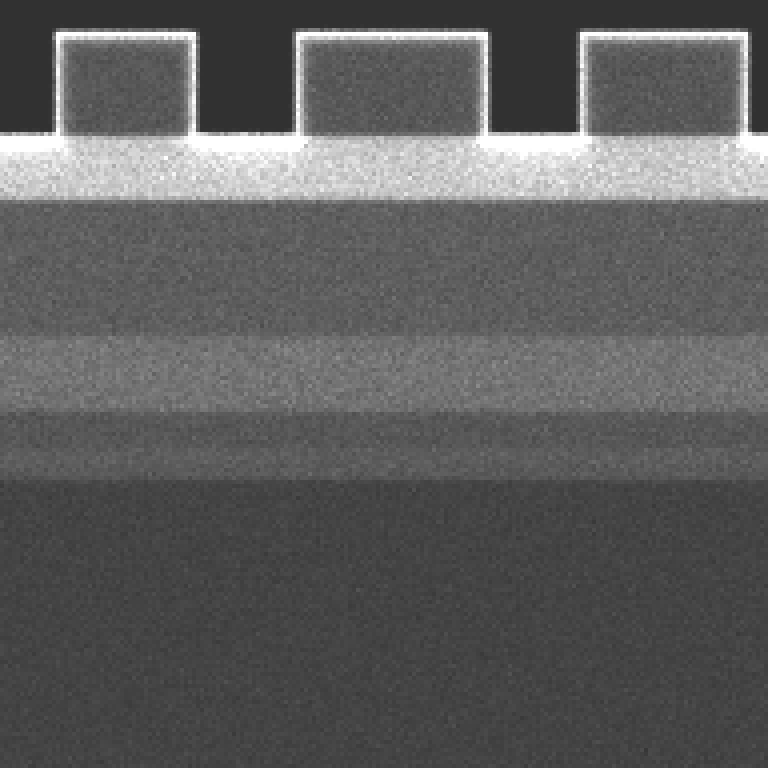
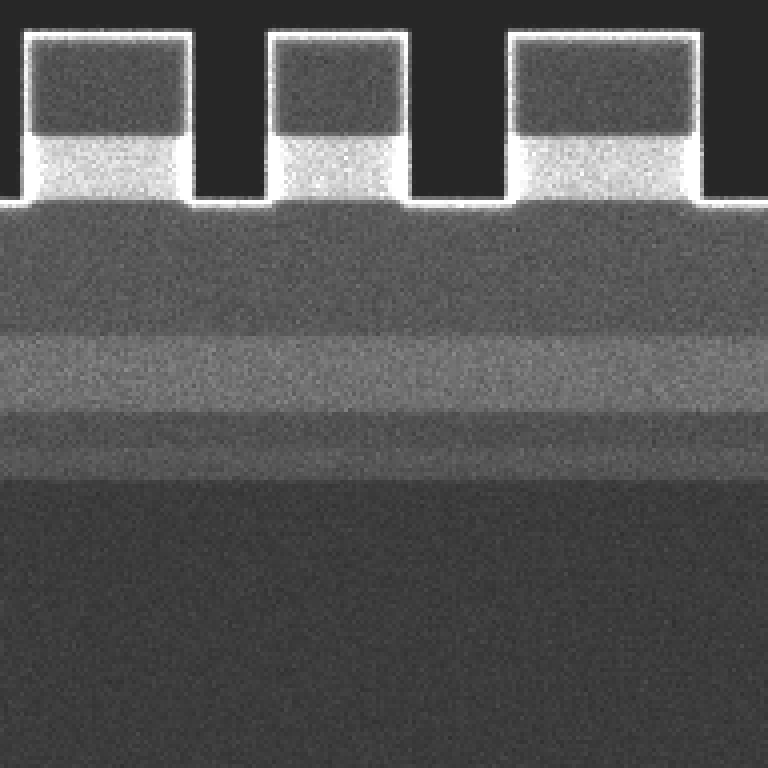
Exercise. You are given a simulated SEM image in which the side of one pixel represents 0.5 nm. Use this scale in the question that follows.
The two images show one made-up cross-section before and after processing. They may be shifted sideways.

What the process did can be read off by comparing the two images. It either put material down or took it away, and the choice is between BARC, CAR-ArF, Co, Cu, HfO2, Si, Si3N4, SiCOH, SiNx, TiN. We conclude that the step removed HfO2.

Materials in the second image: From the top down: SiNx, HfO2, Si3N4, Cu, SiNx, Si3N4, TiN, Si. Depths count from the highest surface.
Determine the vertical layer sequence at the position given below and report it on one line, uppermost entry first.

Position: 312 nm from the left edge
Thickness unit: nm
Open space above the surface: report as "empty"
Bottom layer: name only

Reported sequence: SiNx 52, HfO2 32, Si3N4 68, Cu 38, SiNx 18, Si3N4 8, TiN 8, Si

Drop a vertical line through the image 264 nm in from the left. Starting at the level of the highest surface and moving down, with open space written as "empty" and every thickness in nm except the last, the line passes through SiNx 52, HfO2 32, Si3N4 68, Cu 38, SiNx 18, Si3N4 8, TiN 8, Si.